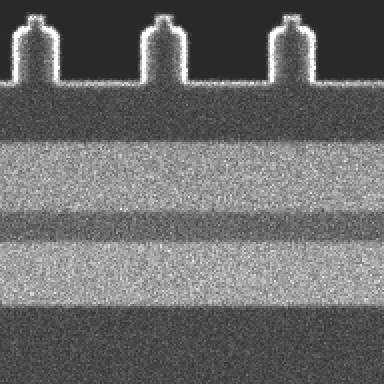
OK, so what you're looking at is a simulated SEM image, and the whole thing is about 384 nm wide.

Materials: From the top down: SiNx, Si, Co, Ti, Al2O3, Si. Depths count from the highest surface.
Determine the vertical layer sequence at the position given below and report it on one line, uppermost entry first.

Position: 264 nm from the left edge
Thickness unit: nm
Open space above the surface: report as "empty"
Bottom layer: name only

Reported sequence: empty 66, Si 60, Co 70, Ti 30, Al2O3 64, Si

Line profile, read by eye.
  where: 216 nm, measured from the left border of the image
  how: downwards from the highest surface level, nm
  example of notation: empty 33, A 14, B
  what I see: empty 66, Si 60, Co 70, Ti 30, Al2O3 64, Si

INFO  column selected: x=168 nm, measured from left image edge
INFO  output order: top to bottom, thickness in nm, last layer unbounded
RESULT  Si 126, Co 70, Ti 30, Al2O3 64, Si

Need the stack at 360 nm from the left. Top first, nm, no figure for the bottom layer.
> empty 66, Si 60, Co 70, Ti 30, Al2O3 64, Si